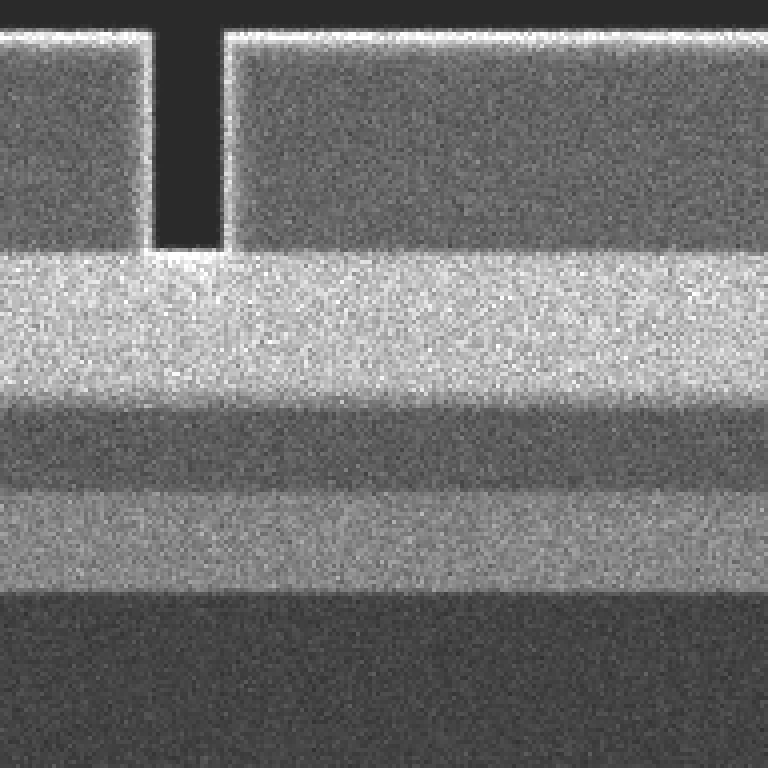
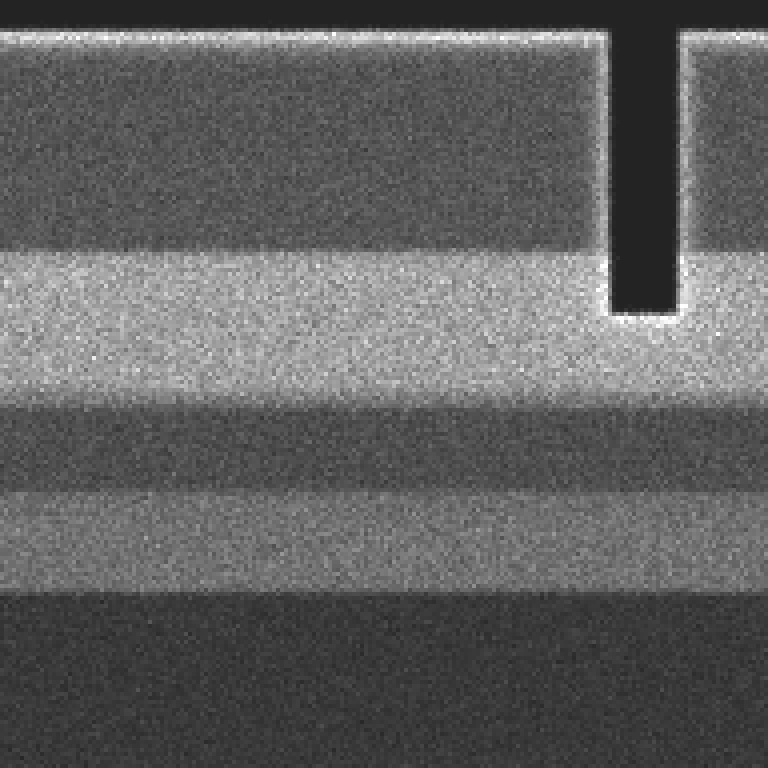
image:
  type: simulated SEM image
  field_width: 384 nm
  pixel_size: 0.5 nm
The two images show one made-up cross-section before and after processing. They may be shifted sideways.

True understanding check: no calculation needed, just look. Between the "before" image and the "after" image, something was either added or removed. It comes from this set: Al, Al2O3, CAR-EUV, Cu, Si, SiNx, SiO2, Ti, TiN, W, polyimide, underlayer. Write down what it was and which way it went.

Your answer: W (removed)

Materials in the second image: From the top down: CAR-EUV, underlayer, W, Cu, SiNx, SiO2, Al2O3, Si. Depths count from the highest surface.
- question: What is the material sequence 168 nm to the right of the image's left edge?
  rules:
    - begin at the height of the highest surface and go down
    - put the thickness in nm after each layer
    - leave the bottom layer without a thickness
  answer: CAR-EUV 64, underlayer 46, W 70, Cu 8, SiNx 42, SiO2 12, Al2O3 38, Si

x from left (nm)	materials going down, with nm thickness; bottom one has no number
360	CAR-EUV 64, underlayer 46, W 70, Cu 8, SiNx 42, SiO2 12, Al2O3 38, Si